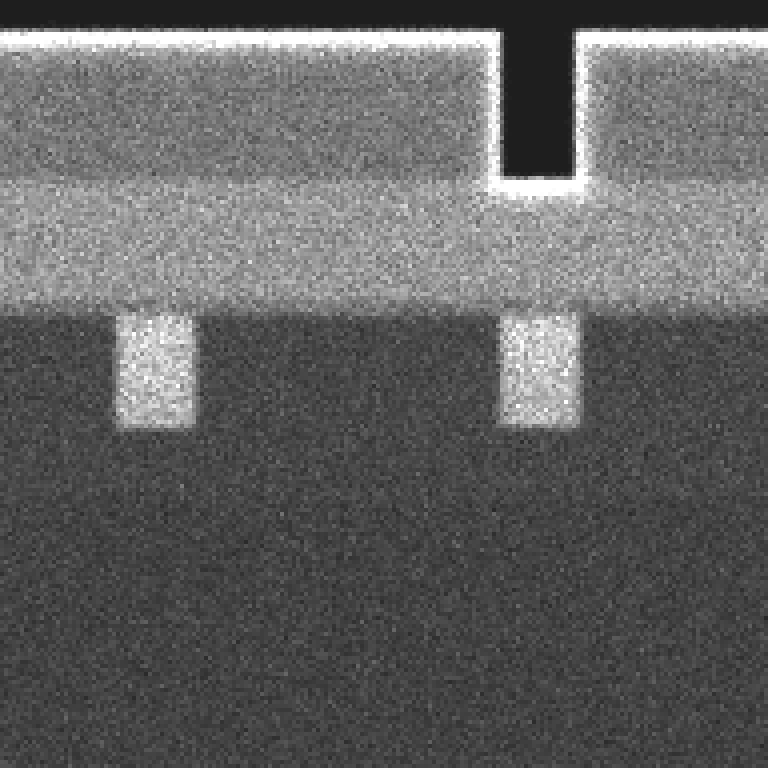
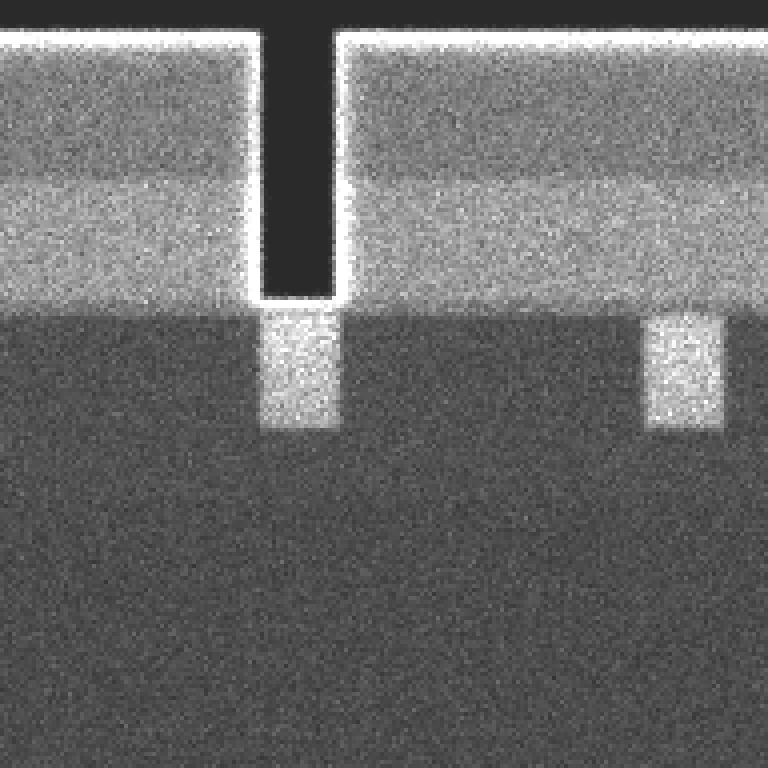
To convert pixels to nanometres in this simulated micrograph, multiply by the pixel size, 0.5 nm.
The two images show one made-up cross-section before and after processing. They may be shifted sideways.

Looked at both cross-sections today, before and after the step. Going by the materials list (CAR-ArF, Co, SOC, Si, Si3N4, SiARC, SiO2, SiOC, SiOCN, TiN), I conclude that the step removed SiO2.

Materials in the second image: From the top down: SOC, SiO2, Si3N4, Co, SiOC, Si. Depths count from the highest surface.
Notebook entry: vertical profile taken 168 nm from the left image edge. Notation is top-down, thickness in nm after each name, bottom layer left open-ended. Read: SOC 74, SiO2 60, Si3N4 8, Co 56, SiOC 36, Si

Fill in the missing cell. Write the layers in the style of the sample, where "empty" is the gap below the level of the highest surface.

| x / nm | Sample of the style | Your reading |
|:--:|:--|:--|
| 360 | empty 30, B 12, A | SOC 74, SiO2 60, Si3N4 8, Co 56, SiOC 36, Si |